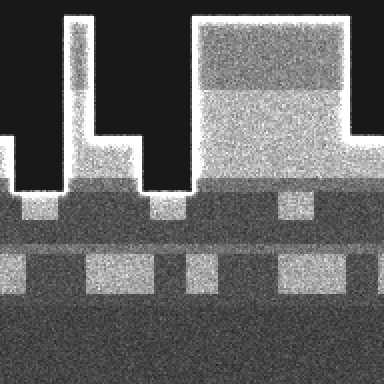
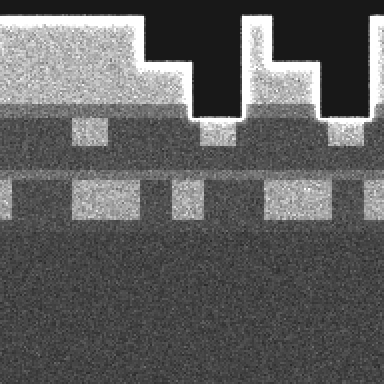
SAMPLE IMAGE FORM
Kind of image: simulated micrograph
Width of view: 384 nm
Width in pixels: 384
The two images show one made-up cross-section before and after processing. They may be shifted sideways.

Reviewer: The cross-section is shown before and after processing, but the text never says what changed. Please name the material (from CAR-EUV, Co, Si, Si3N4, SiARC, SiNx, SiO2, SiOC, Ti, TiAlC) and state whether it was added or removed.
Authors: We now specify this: SiARC, removed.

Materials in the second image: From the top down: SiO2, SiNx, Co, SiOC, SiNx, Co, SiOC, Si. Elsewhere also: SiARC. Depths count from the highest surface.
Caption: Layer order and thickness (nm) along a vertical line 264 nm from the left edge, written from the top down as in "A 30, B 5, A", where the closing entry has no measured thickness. SiO2 88, SiNx 14, SiOC 52, SiNx 10, Co 40, SiOC 12, Si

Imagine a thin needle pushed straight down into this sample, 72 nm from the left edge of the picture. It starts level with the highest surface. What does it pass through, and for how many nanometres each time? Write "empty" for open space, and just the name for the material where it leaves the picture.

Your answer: SiO2 88, SiNx 14, Co 28, SiOC 24, SiNx 10, Co 40, SiOC 12, Si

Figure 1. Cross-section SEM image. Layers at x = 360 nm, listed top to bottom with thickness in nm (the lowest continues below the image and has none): empty 102, Co 28, SiOC 24, SiNx 10, SiOC 52, Si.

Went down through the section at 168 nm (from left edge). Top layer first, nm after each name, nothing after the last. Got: empty 46, SiO2 42, SiNx 14, SiOC 52, SiNx 10, SiOC 52, Si